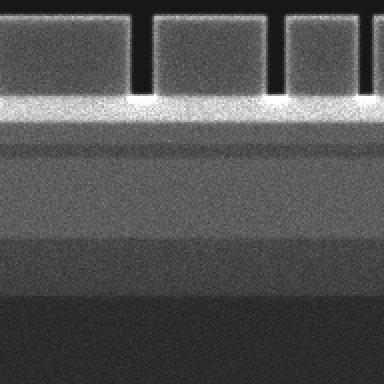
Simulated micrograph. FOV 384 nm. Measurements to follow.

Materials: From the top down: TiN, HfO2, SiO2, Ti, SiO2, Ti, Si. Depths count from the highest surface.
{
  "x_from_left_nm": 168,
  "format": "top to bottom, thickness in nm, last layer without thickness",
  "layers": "TiN 80, HfO2 26, SiO2 22, Ti 14, SiO2 80, Ti 58, Si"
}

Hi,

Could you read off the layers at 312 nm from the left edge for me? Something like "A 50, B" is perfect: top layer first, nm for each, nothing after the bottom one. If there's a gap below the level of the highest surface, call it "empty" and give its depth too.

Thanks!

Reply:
TiN 80, HfO2 26, SiO2 22, Ti 14, SiO2 80, Ti 58, Si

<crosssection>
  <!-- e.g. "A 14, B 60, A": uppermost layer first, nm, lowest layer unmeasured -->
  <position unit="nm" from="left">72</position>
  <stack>TiN 80, HfO2 26, SiO2 22, Ti 14, SiO2 80, Ti 58, Si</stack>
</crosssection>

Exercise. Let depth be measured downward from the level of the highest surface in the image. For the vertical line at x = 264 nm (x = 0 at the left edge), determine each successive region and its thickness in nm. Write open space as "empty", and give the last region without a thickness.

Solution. TiN 80, HfO2 26, SiO2 22, Ti 14, SiO2 80, Ti 58, Si